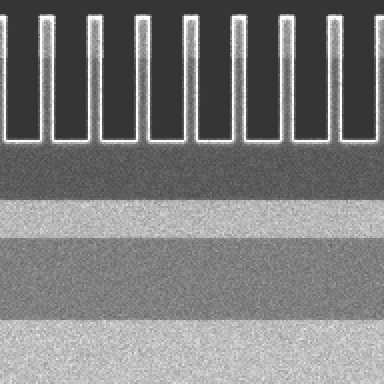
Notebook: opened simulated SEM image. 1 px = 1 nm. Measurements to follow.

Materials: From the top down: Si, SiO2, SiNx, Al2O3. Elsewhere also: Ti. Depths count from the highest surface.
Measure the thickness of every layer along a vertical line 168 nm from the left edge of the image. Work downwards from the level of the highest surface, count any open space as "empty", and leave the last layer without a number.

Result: empty 124, Si 60, SiO2 38, SiNx 82, Al2O3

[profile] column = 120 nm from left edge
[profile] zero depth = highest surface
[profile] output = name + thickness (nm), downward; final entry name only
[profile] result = empty 124, Si 60, SiO2 38, SiNx 82, Al2O3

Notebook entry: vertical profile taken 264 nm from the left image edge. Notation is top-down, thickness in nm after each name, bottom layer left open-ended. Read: empty 124, Si 60, SiO2 38, SiNx 82, Al2O3